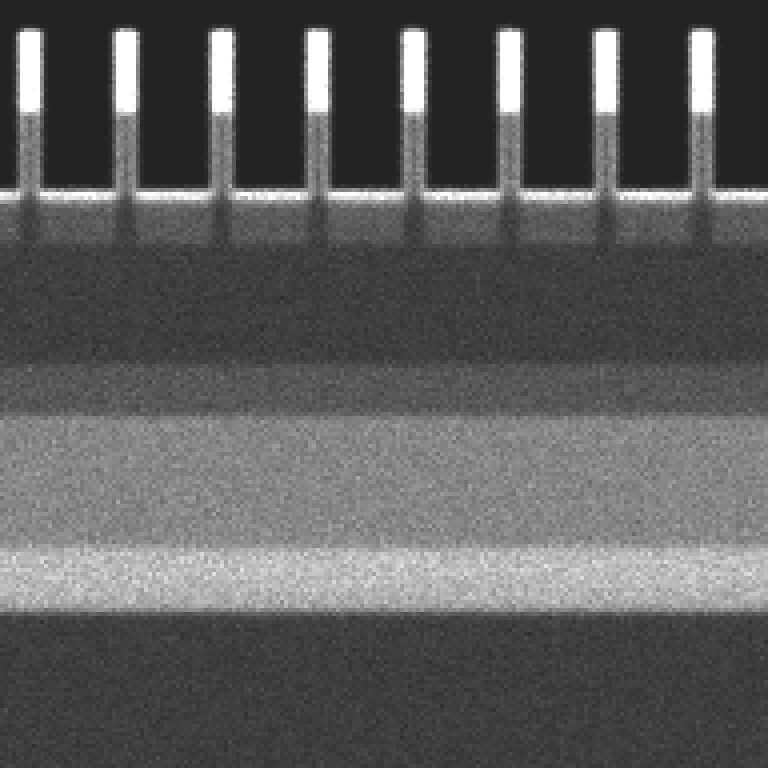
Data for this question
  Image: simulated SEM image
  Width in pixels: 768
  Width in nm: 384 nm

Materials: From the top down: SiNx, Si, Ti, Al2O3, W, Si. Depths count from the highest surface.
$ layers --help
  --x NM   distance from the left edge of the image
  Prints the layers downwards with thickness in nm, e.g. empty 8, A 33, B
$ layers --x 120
empty 80, SiNx 26, Si 60, Ti 26, Al2O3 66, W 32, Si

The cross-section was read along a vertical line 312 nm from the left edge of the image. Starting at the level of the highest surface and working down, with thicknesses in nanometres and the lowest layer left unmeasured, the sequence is empty 80, SiNx 26, Si 60, Ti 26, Al2O3 66, W 32, Si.